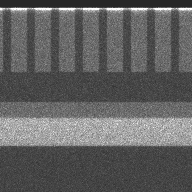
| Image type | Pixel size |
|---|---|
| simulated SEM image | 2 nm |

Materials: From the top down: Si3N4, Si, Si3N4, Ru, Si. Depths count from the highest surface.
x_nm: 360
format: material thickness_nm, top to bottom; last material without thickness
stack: Si3N4 128, Si 60, Si3N4 32, Ru 56, Si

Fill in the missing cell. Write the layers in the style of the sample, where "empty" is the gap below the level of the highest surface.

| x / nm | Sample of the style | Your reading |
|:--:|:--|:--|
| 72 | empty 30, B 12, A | Si3N4 128, Si 60, Si3N4 32, Ru 56, Si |